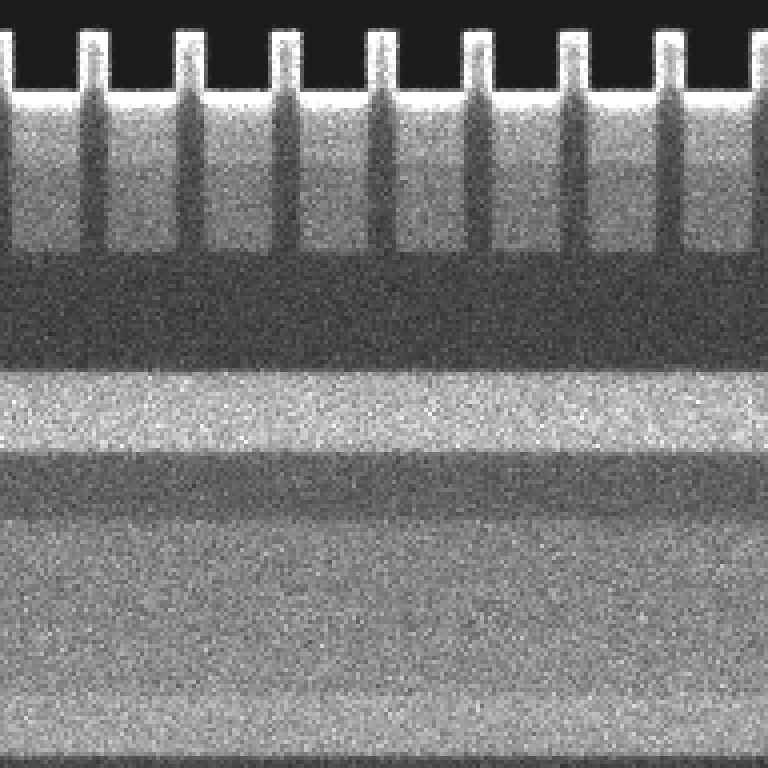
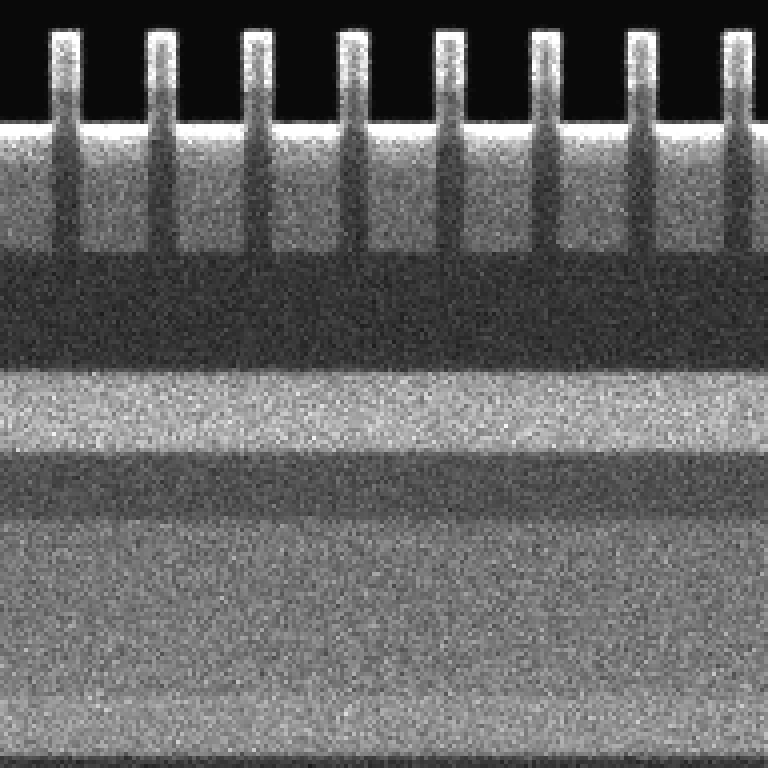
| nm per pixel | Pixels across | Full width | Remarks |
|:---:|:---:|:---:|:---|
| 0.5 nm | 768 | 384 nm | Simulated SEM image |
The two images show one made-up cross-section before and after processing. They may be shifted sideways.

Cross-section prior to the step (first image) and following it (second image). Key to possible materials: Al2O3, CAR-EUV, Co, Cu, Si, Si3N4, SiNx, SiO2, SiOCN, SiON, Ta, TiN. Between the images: SiO2 was removed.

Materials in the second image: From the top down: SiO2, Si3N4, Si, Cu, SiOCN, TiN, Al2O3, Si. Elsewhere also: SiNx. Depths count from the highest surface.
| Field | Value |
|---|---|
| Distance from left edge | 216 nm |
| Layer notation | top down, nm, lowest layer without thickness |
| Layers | empty 46, SiO2 20, Si3N4 44, Si 60, Cu 40, SiOCN 34, TiN 88, Al2O3 30, Si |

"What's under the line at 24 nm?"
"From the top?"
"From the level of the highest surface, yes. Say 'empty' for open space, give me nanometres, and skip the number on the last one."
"empty 46, SiO2 20, Si3N4 44, Si 60, Cu 40, SiOCN 34, TiN 88, Al2O3 30, Si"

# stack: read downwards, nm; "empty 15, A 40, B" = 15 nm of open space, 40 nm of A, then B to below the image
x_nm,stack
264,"empty 46, SiO2 20, Si3N4 44, Si 60, Cu 40, SiOCN 34, TiN 88, Al2O3 30, Si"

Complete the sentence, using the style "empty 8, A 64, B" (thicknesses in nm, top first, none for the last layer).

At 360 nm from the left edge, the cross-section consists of empty 46, SiO2 20, Si3N4 44, Si 60, Cu 40, SiOCN 34, TiN 88, Al2O3 30, Si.